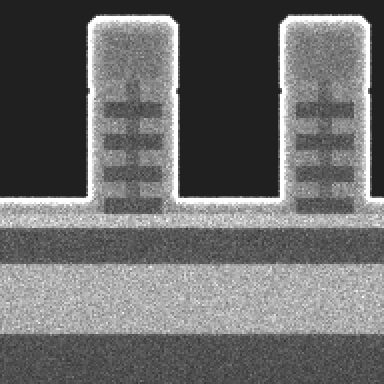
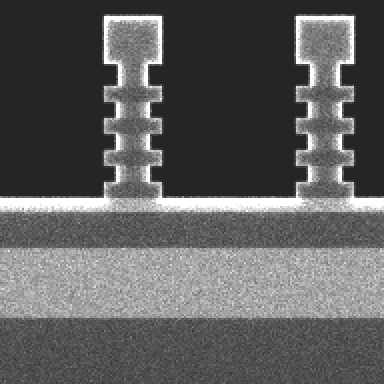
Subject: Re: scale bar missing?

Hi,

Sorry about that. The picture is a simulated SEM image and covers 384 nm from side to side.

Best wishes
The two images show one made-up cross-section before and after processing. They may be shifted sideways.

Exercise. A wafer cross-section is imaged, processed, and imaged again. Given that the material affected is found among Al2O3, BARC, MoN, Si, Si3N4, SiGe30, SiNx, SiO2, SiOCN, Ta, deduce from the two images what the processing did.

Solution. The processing removed Si3N4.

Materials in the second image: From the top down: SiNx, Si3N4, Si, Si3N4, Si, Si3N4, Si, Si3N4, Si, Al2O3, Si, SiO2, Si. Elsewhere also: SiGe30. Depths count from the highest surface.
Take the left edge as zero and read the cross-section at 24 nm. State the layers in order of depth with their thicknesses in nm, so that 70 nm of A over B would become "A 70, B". empty 182, Al2O3 14, Si 36, SiO2 70, Si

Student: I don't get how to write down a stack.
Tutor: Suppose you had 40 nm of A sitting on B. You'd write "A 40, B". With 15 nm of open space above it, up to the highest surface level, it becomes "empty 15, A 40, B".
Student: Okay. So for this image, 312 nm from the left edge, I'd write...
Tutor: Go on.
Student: SiNx 48, Si3N4 22, Si 16, Si3N4 16, Si 16, Si3N4 16, Si 16, Si3N4 16, Si 16, Al2O3 14, Si 36, SiO2 70, Si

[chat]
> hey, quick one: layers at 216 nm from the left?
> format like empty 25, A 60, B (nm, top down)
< empty 182, Al2O3 14, Si 36, SiO2 70, Si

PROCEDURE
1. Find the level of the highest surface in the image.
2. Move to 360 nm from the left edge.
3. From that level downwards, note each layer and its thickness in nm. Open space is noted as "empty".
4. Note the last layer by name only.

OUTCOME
empty 182, Al2O3 14, Si 36, SiO2 70, Si